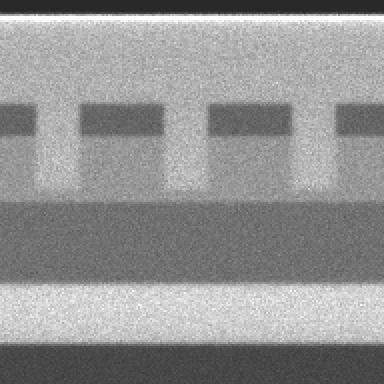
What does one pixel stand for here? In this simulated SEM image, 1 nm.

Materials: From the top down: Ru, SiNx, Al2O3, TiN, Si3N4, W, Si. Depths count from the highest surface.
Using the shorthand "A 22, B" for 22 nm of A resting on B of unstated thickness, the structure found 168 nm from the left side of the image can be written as Ru 174, Al2O3 12, TiN 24, Si3N4 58, W 60, Si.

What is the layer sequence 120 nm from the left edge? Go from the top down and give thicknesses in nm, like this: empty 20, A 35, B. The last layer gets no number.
Ru 88, SiNx 32, Al2O3 66, TiN 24, Si3N4 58, W 60, Si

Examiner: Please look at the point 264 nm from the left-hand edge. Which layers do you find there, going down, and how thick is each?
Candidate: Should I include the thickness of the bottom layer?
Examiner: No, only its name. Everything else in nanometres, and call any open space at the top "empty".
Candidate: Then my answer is Ru 88, SiNx 32, Al2O3 66, TiN 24, Si3N4 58, W 60, Si